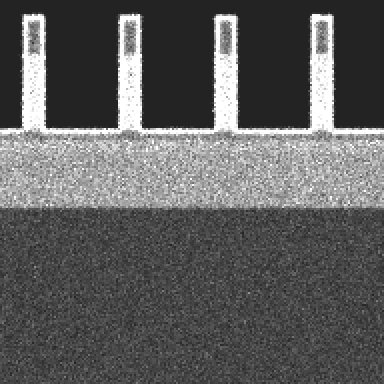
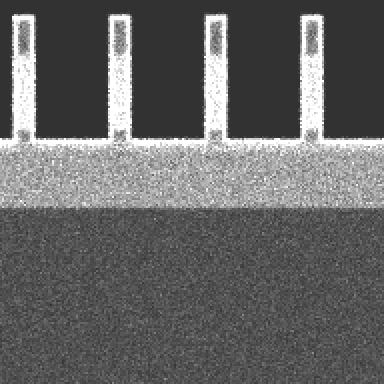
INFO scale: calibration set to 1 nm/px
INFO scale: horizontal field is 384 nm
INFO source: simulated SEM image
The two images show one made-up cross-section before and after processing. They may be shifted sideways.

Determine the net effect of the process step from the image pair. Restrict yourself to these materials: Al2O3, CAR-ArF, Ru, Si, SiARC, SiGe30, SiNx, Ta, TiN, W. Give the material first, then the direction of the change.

TiN: removed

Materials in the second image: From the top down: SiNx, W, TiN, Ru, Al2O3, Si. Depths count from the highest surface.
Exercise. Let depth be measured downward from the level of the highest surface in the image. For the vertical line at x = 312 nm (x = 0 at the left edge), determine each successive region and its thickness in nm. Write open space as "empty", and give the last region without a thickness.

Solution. SiNx 38, W 76, TiN 10, Ru 12, Al2O3 56, Si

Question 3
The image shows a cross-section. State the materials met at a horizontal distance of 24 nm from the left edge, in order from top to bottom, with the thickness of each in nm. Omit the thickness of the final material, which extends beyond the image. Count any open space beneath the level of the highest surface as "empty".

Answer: SiNx 38, W 76, TiN 10, Ru 12, Al2O3 56, Si